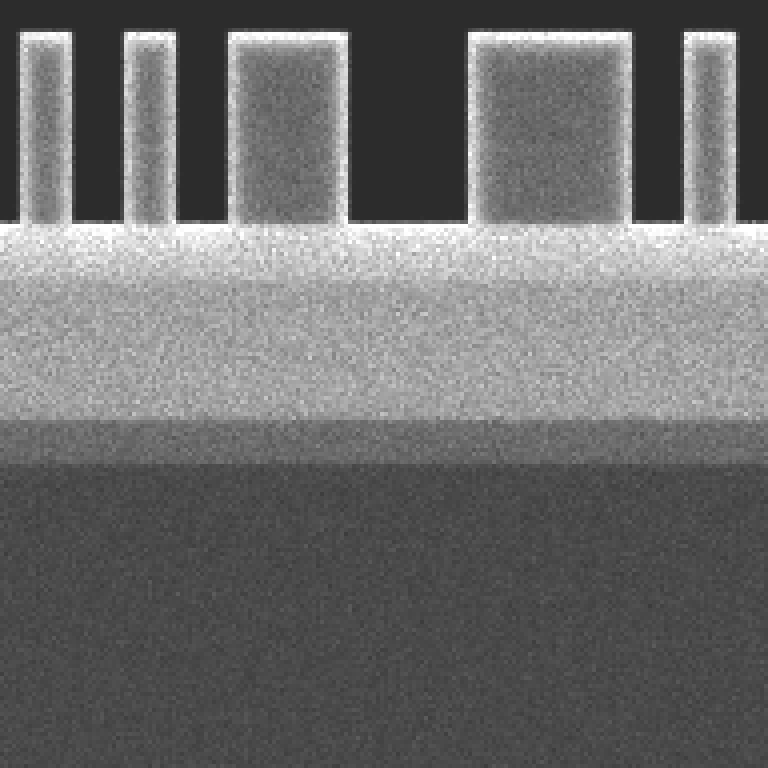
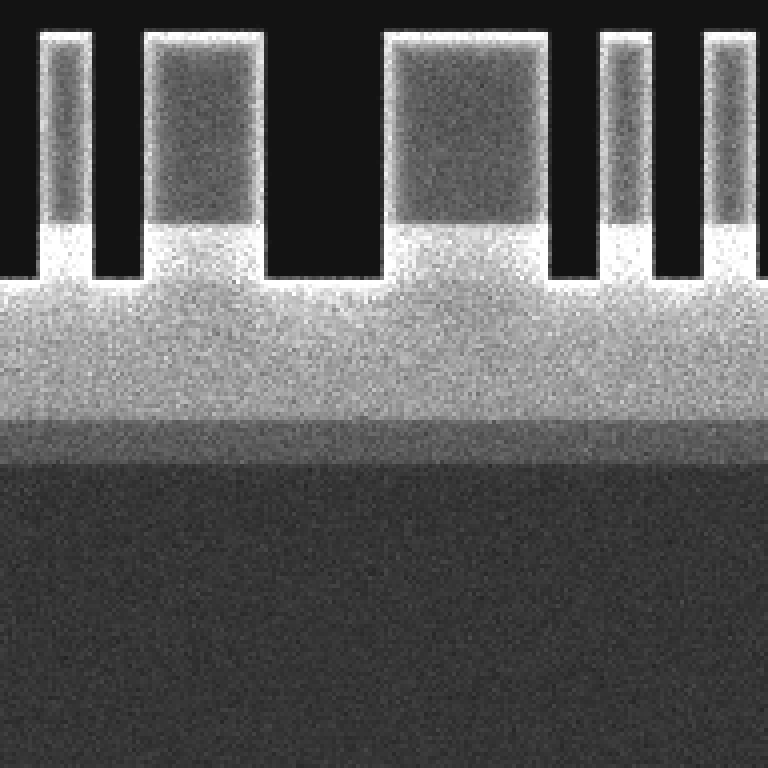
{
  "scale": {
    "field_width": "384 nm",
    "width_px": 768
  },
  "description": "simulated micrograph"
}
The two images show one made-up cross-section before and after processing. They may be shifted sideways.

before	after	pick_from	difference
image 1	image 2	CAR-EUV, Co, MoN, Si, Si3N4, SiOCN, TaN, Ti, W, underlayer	W removed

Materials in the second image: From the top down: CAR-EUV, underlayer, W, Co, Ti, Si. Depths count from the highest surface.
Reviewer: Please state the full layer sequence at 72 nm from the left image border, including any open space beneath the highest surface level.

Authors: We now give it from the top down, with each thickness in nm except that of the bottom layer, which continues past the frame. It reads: CAR-EUV 54, underlayer 42, W 28, Co 70, Ti 22, Si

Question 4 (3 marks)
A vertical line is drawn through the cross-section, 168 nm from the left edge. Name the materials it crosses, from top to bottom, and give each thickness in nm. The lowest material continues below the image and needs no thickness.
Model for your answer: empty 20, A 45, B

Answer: empty 124, Co 70, Ti 22, Si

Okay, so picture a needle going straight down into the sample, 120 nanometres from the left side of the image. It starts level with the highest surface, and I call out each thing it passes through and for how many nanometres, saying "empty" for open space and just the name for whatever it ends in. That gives CAR-EUV 54, underlayer 42, W 28, Co 70, Ti 22, Si